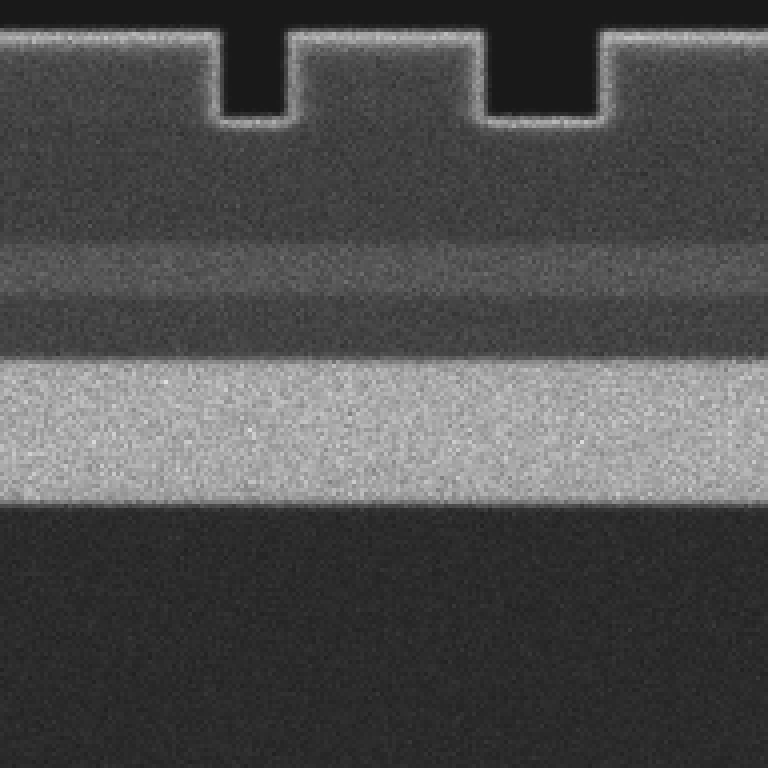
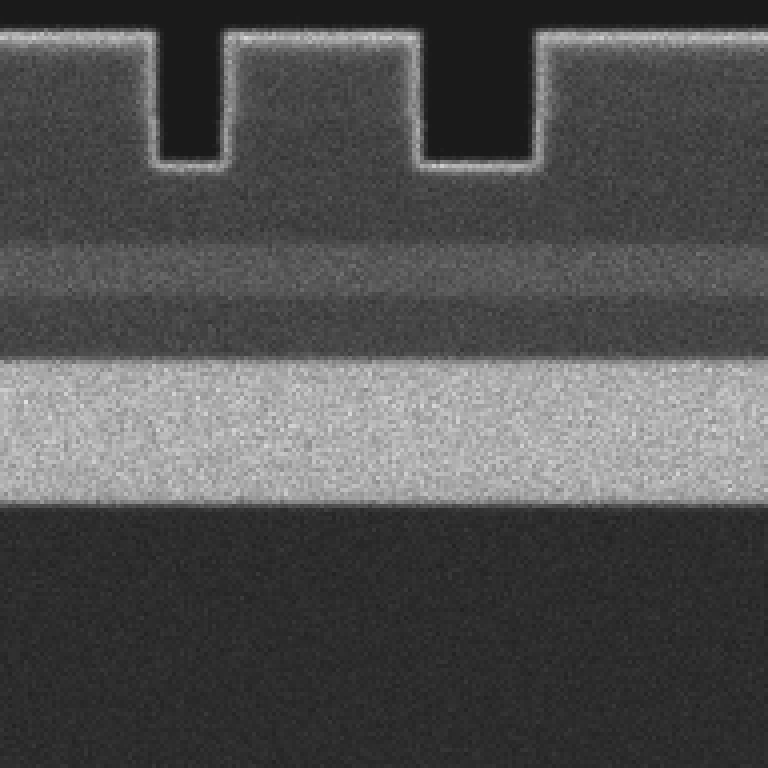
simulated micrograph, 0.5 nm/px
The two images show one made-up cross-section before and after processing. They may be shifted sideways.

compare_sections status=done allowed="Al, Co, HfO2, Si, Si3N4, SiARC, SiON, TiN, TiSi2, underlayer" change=removed material="TiN"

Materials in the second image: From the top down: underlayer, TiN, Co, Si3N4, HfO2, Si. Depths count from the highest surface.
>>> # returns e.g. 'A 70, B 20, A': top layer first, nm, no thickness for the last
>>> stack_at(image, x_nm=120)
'underlayer 44, TiN 62, Co 26, Si3N4 32, HfO2 72, Si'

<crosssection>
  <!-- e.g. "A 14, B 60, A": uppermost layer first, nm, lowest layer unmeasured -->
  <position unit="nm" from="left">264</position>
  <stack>empty 66, TiN 40, Co 26, Si3N4 32, HfO2 72, Si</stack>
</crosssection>